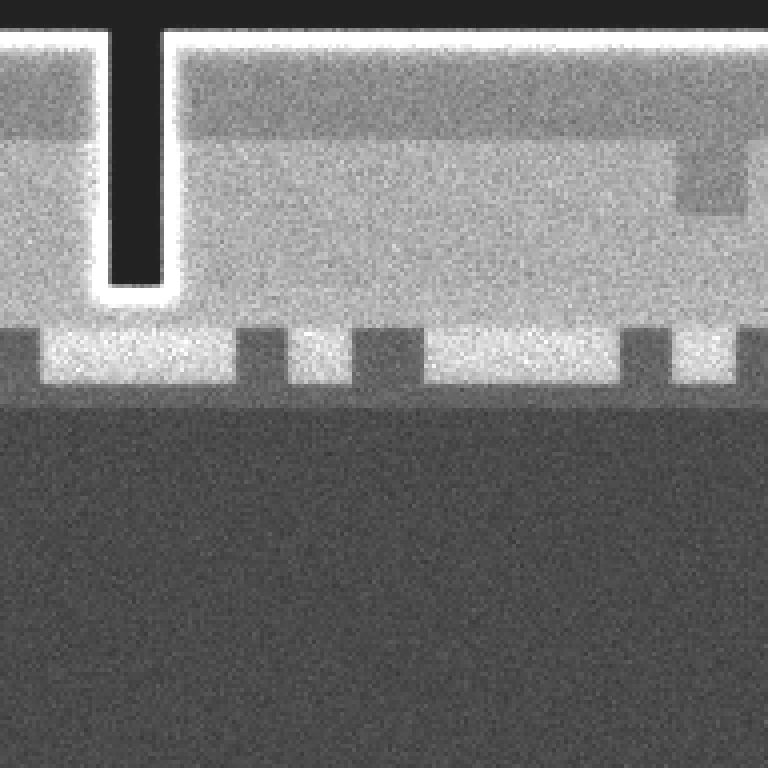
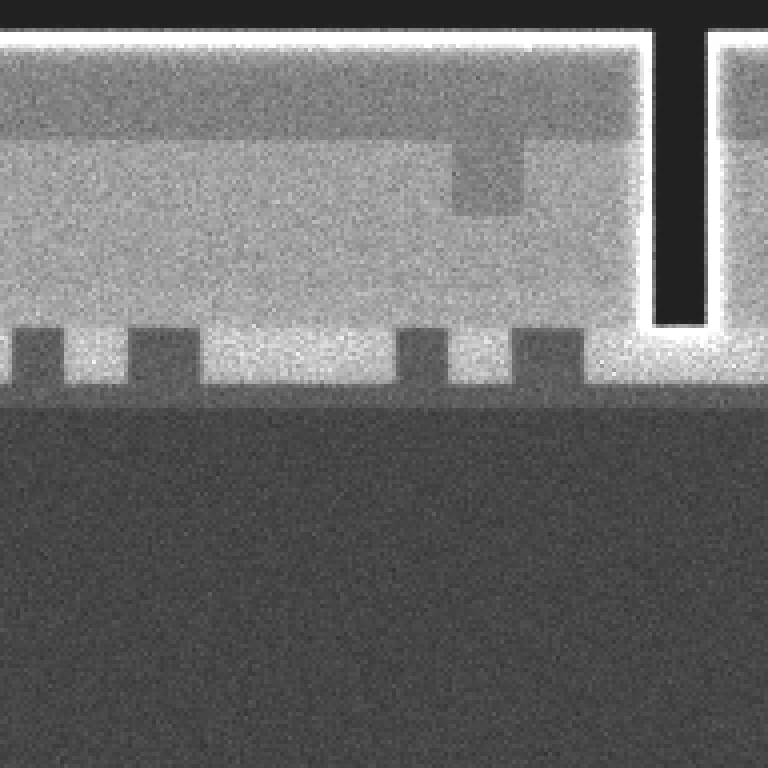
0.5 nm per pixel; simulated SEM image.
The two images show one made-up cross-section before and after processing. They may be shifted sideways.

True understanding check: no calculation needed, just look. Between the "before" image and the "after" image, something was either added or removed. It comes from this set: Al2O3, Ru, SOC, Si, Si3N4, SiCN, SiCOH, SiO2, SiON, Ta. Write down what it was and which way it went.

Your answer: Al2O3 (removed)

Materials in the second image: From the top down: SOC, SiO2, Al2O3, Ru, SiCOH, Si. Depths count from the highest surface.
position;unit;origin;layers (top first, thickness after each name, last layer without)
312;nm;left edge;SOC 54, SiO2 74, Al2O3 20, Ru 28, SiCOH 12, Si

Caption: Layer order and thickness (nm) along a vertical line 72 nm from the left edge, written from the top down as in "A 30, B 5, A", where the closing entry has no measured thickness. SOC 54, SiO2 74, Al2O3 20, SiCOH 40, Si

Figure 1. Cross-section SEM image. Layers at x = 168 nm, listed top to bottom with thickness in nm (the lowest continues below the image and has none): SOC 54, SiO2 74, Al2O3 20, Ru 28, SiCOH 12, Si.